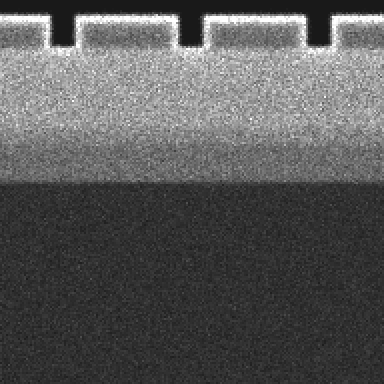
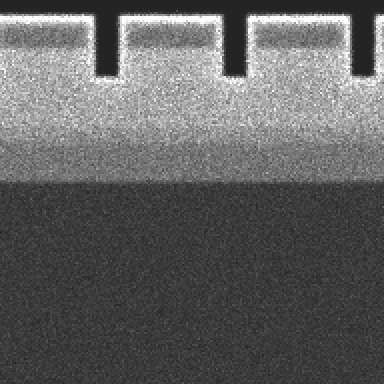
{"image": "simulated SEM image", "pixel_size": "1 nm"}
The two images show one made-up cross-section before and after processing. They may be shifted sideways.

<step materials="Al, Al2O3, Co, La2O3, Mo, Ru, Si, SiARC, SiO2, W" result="removed W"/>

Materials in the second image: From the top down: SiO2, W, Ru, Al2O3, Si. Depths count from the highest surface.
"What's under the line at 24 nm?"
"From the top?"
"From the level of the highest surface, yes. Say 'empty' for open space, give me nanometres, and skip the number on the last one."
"SiO2 32, W 80, Ru 16, Al2O3 38, Si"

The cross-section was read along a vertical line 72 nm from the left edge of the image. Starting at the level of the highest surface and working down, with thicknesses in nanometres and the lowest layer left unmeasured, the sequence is SiO2 32, W 80, Ru 16, Al2O3 38, Si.